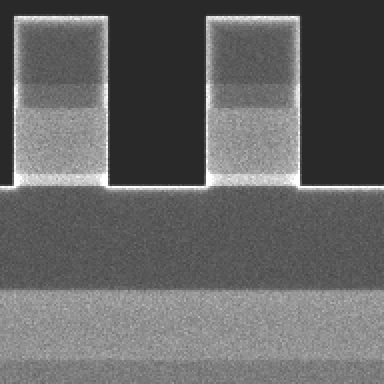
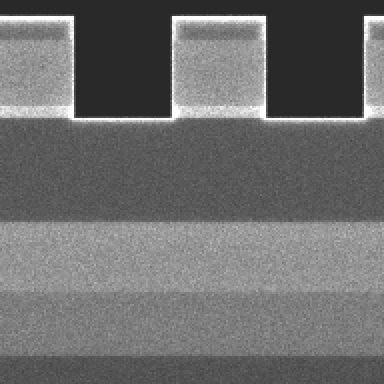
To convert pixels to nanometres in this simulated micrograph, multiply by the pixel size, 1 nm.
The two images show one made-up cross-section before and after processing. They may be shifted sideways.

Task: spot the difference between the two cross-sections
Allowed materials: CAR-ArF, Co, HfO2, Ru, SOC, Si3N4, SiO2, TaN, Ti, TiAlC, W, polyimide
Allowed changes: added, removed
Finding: removed SOC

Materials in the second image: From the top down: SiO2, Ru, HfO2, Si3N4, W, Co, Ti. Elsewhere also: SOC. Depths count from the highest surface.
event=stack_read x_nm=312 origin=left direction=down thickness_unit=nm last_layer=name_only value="empty 102, Si3N4 104, W 70, Co 64, Ti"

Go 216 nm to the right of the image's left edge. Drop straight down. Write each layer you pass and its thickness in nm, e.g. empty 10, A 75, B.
SiO2 24, Ru 66, HfO2 12, Si3N4 104, W 70, Co 64, Ti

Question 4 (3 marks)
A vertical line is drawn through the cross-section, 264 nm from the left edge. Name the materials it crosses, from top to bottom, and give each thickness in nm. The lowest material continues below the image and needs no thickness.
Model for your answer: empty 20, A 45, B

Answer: SiO2 24, Ru 66, HfO2 12, Si3N4 104, W 70, Co 64, Ti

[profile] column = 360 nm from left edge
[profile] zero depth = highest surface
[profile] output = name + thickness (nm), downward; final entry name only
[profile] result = empty 102, Si3N4 104, W 70, Co 64, Ti